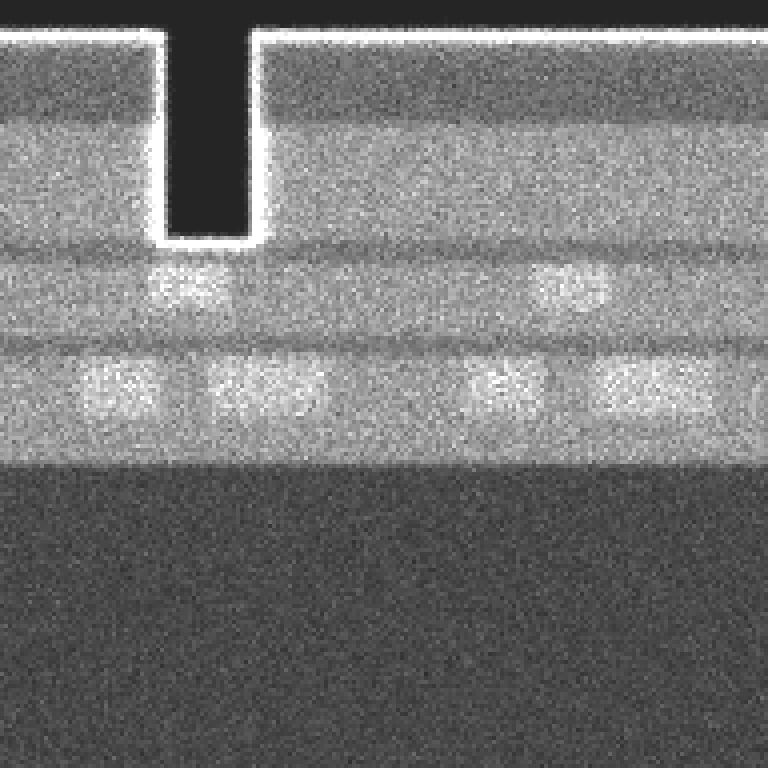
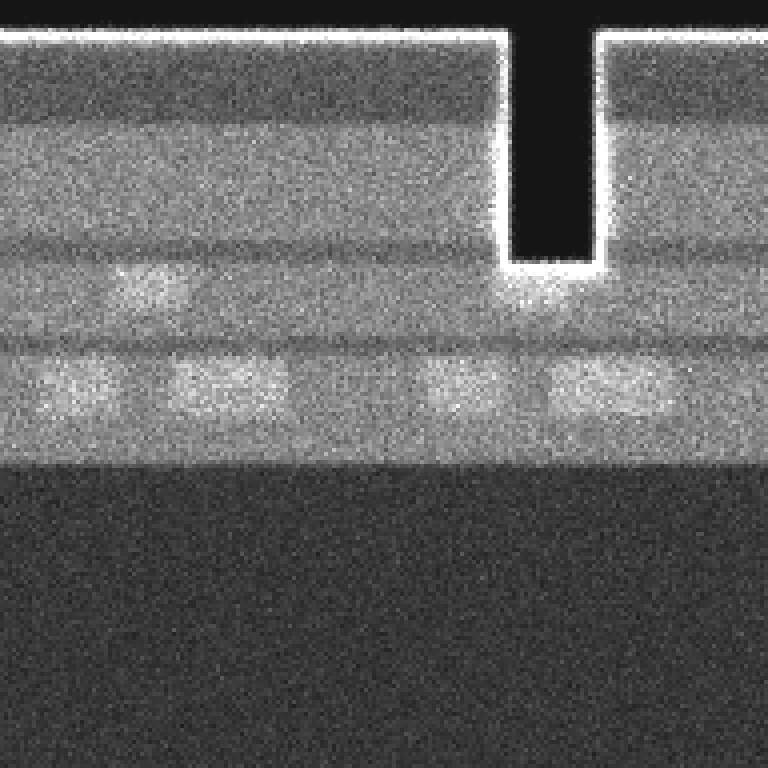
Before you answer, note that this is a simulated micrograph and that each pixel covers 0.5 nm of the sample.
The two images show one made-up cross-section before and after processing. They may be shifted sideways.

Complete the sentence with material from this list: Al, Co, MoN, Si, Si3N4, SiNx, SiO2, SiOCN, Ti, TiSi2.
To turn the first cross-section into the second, Si3N4 must be removed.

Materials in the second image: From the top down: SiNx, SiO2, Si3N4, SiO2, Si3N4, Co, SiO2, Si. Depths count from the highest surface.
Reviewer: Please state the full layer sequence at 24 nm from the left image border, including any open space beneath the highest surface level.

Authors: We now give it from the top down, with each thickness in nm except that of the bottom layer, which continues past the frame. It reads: SiNx 46, SiO2 58, Si3N4 12, SiO2 36, Si3N4 10, Co 30, SiO2 24, Si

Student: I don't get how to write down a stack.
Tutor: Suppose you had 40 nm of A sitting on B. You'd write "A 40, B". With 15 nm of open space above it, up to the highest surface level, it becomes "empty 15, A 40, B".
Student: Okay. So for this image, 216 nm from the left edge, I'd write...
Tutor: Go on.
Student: SiNx 46, SiO2 58, Si3N4 12, SiO2 36, Si3N4 10, Co 30, SiO2 24, Si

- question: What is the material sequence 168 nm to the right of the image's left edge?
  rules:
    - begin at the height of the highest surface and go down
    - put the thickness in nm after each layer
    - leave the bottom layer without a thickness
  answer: SiNx 46, SiO2 58, Si3N4 12, SiO2 36, Si3N4 10, SiO2 54, Si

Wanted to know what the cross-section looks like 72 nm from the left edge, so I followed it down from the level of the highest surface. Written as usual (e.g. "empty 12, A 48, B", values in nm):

SiNx 46, SiO2 58, Si3N4 12, Co 22, SiO2 14, Si3N4 10, SiO2 54, Si